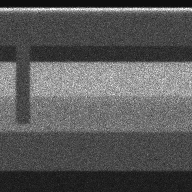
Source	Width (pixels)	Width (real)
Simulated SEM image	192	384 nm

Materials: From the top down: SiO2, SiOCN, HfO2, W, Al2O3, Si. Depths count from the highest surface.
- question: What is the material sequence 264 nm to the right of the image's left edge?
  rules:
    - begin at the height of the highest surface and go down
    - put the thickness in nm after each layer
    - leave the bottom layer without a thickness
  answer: SiO2 76, SiOCN 32, HfO2 68, W 72, Al2O3 78, Si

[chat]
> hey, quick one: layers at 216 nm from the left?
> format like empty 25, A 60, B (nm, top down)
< SiO2 76, SiOCN 32, HfO2 68, W 72, Al2O3 78, Si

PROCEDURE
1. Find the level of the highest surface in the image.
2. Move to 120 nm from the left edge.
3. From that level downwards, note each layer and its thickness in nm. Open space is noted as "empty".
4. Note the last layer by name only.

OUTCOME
SiO2 76, SiOCN 32, HfO2 68, W 72, Al2O3 78, Si